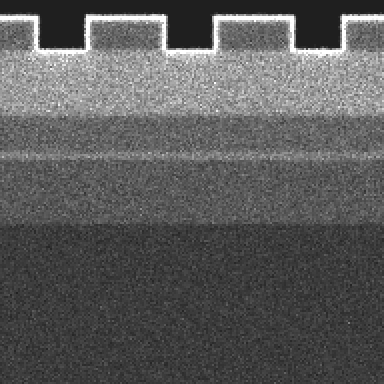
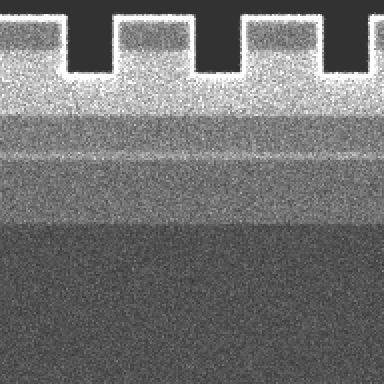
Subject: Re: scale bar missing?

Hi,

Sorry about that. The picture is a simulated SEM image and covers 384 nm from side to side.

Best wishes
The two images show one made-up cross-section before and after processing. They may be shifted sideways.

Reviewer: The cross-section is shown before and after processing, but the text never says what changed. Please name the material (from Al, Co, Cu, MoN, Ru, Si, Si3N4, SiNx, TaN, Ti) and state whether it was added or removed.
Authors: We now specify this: Ru, removed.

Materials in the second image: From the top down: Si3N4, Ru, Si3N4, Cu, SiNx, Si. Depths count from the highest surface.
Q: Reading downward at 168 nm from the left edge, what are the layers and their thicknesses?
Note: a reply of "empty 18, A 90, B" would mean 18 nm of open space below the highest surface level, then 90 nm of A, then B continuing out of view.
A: Si3N4 34, Ru 66, Si3N4 36, Cu 8, SiNx 64, Si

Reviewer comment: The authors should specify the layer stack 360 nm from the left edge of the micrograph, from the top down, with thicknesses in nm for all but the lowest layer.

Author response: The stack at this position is empty 58, Ru 42, Si3N4 36, Cu 8, SiNx 64, Si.